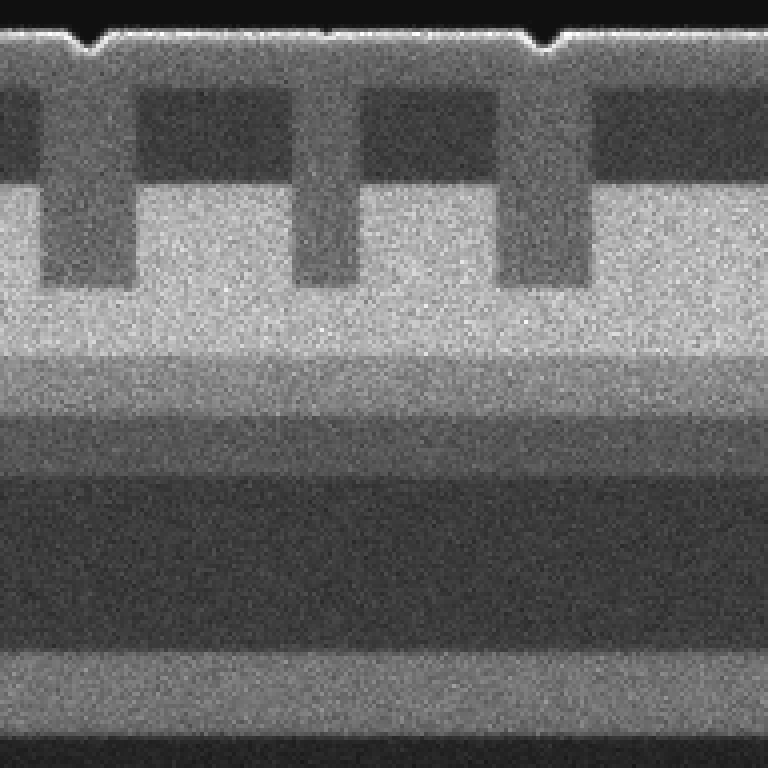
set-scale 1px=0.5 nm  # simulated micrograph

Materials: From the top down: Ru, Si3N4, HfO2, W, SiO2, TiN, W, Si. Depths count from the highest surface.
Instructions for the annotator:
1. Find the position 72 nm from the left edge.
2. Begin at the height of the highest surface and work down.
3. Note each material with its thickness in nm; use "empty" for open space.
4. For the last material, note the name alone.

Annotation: Ru 28, Si3N4 48, HfO2 86, W 30, SiO2 30, TiN 88, W 42, Si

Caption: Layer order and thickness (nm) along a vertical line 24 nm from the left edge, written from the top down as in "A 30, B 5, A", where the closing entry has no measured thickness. Ru 128, HfO2 34, W 30, SiO2 30, TiN 88, W 42, Si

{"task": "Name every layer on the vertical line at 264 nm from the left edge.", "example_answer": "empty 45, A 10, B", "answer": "empty 4, Ru 124, HfO2 34, W 30, SiO2 30, TiN 88, W 42, Si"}